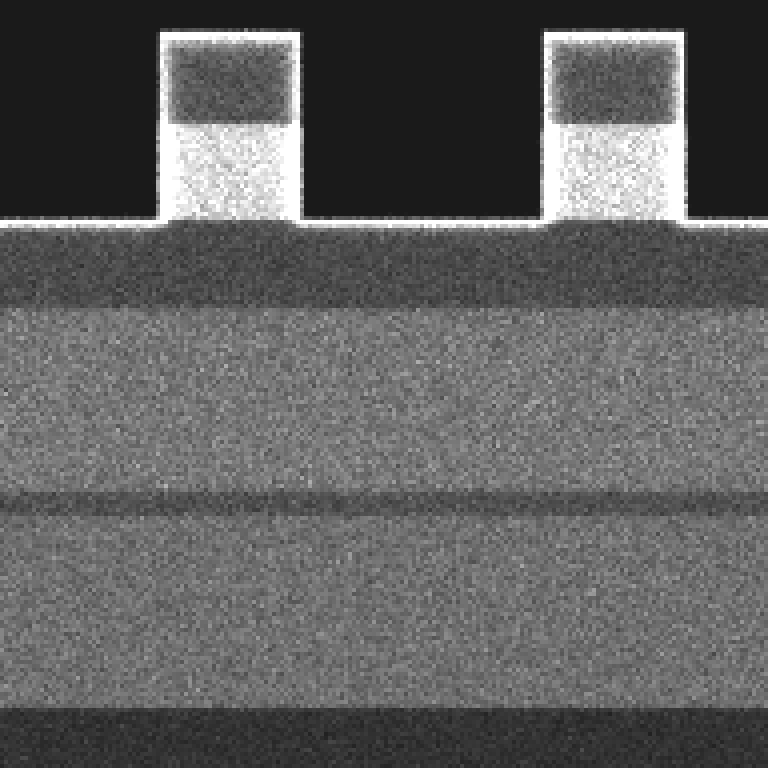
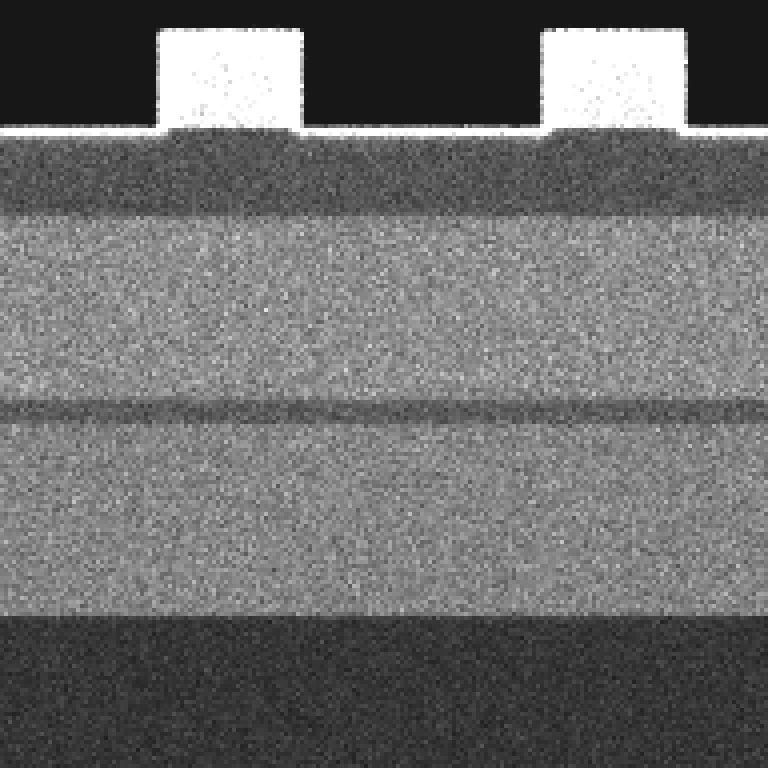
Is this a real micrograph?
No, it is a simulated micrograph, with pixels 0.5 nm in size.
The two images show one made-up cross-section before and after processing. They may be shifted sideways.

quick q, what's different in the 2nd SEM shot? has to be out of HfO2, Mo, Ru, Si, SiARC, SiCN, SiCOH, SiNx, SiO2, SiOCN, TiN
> SiARC removed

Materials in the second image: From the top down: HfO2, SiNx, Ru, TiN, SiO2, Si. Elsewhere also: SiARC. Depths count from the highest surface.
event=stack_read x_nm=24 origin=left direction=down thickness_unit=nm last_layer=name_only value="empty 48, SiNx 44, Ru 92, TiN 12, SiO2 96, Si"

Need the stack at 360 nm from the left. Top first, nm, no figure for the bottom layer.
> empty 48, SiNx 44, Ru 92, TiN 12, SiO2 96, Si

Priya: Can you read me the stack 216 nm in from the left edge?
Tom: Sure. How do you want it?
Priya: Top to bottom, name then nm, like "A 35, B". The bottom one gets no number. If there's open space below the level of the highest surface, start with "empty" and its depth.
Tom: empty 48, SiNx 44, Ru 92, TiN 12, SiO2 96, Si